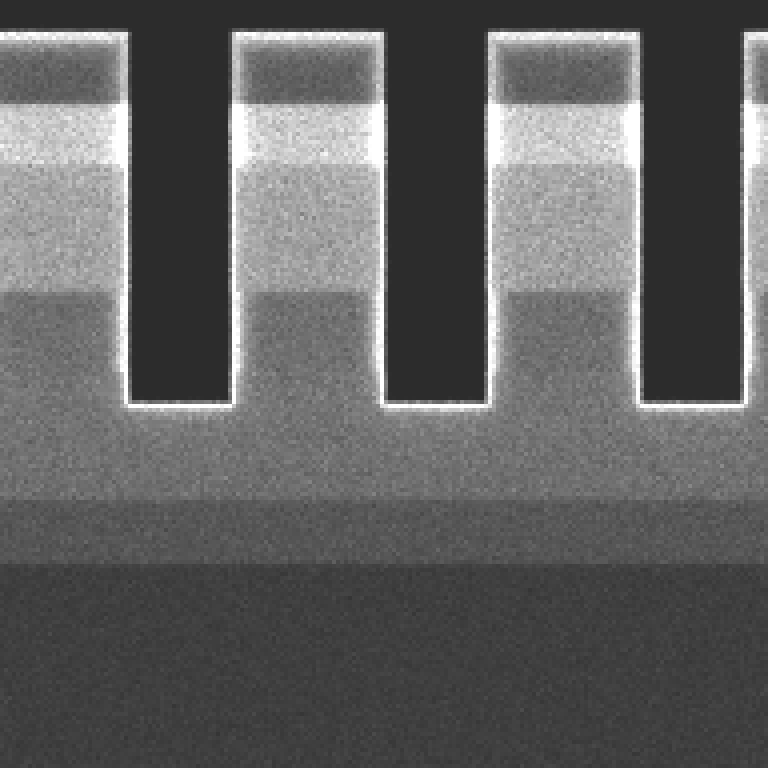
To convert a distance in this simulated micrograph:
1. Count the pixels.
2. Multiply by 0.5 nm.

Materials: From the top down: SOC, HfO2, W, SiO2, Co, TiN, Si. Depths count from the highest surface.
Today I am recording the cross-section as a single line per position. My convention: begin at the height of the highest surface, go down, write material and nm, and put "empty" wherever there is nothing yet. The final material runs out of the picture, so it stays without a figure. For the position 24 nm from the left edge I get SOC 36, HfO2 30, W 64, SiO2 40, Co 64, TiN 32, Si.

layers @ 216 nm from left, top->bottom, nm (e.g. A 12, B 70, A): empty 186, Co 48, TiN 32, Si